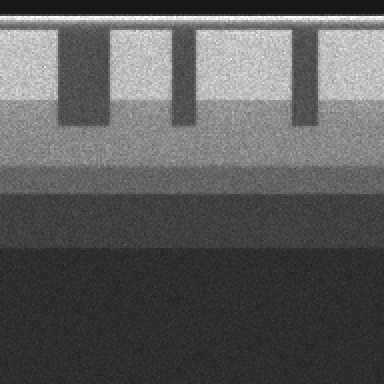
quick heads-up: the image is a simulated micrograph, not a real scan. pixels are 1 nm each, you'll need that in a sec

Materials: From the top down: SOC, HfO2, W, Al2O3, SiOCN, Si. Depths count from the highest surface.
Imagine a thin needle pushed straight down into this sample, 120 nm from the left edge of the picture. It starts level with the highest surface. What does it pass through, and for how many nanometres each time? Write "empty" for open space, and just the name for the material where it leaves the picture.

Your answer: SOC 14, HfO2 70, W 66, Al2O3 28, SiOCN 54, Si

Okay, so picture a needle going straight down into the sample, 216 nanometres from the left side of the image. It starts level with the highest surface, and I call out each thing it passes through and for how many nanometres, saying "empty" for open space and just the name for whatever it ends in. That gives SOC 14, HfO2 70, W 66, Al2O3 28, SiOCN 54, Si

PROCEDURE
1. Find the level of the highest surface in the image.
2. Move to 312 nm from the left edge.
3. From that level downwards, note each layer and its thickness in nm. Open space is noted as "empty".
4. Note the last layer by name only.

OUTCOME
SOC 110, W 40, Al2O3 28, SiOCN 54, Si